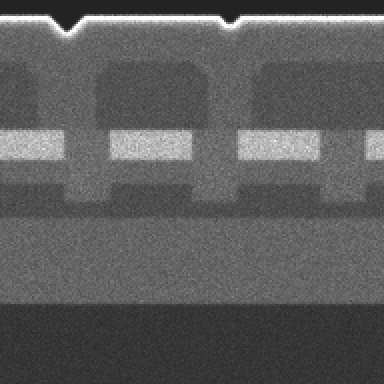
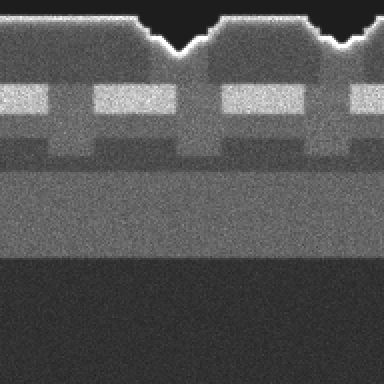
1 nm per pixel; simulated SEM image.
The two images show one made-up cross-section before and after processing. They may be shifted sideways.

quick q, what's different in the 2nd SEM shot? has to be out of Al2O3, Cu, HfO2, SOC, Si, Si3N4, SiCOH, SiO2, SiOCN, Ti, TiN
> SiO2 removed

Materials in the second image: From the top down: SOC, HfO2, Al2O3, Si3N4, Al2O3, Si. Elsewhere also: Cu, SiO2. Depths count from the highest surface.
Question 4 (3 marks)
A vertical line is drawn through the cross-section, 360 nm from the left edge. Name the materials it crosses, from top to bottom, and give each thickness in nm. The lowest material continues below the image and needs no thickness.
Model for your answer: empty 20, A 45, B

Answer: empty 20, SiO2 48, HfO2 30, Al2O3 24, Si3N4 34, Al2O3 86, Si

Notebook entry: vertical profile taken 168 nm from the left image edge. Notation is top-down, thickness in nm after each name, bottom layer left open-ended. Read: empty 28, SiO2 40, HfO2 30, Al2O3 24, Si3N4 34, Al2O3 86, Si